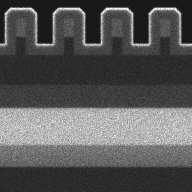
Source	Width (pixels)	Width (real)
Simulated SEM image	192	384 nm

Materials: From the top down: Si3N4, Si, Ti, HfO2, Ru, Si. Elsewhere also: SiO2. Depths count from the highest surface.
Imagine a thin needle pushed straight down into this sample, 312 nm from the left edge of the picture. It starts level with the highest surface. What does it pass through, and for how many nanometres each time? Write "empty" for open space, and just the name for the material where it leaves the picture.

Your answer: Si3N4 94, Si 60, Ti 46, HfO2 74, Ru 44, Si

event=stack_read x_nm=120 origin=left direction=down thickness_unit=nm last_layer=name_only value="Si3N4 94, Si 60, Ti 46, HfO2 74, Ru 44, Si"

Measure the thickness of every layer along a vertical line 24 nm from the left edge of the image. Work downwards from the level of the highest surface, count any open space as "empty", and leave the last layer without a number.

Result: Si3N4 94, Si 60, Ti 46, HfO2 74, Ru 44, Si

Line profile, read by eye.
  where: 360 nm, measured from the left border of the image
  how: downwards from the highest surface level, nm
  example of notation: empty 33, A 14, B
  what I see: empty 10, Si3N4 84, Si 60, Ti 46, HfO2 74, Ru 44, Si